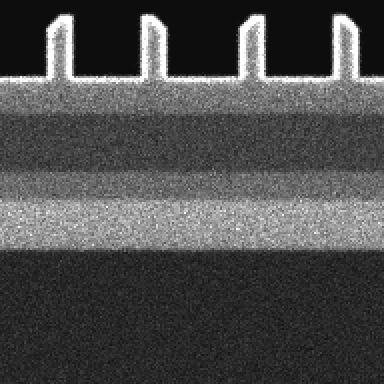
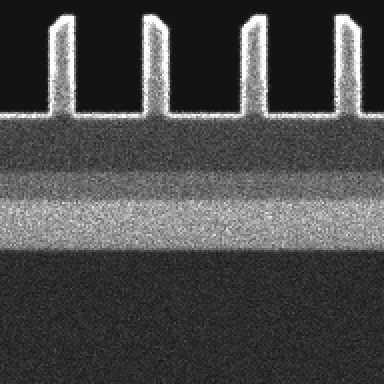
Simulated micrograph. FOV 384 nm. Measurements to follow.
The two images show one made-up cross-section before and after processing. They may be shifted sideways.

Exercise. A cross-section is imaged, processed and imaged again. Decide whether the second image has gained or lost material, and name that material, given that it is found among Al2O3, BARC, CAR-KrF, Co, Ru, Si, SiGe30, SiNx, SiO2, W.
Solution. removed: Co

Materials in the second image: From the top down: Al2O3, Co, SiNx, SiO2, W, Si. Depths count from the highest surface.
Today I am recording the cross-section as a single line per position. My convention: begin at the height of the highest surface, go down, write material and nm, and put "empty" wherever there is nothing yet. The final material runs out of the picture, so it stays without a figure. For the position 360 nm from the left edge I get empty 98, SiNx 58, SiO2 28, W 50, Si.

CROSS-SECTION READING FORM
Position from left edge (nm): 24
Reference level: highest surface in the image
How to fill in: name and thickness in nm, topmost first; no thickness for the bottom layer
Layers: empty 98, SiNx 58, SiO2 28, W 50, Si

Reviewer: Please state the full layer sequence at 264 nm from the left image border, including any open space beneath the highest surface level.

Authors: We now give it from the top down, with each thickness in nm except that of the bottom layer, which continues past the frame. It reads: Al2O3 62, Co 36, SiNx 58, SiO2 28, W 50, Si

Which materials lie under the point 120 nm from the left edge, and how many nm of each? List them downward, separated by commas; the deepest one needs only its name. empty 98, SiNx 58, SiO2 28, W 50, Si